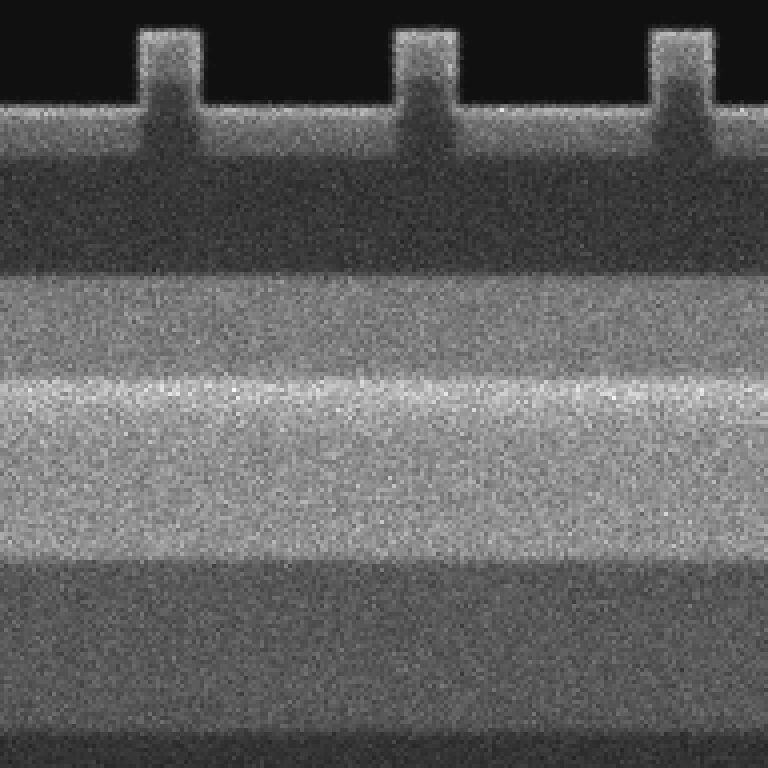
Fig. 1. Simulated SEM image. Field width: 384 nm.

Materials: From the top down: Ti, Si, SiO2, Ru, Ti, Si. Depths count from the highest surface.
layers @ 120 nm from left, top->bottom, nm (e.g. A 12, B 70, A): empty 38, Ti 24, Si 60, SiO2 52, Ru 90, Ti 86, Si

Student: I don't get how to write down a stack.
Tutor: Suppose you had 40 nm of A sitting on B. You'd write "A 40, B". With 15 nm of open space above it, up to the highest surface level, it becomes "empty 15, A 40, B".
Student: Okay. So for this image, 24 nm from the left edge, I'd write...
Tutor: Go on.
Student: empty 38, Ti 24, Si 60, SiO2 52, Ru 90, Ti 86, Si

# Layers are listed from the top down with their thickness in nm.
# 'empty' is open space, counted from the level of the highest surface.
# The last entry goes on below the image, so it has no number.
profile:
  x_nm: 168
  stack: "empty 38, Ti 24, Si 60, SiO2 52, Ru 90, Ti 86, Si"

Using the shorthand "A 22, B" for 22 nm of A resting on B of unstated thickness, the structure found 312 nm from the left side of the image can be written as empty 38, Ti 24, Si 60, SiO2 52, Ru 90, Ti 86, Si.